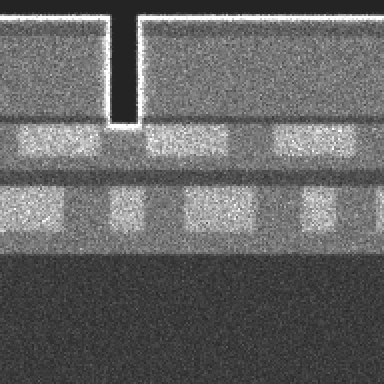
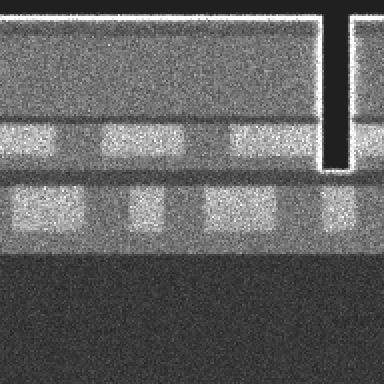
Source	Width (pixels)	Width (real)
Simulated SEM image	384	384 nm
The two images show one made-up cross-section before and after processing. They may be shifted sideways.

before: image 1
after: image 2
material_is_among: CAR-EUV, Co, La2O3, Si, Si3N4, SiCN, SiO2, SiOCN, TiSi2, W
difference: SiO2, removed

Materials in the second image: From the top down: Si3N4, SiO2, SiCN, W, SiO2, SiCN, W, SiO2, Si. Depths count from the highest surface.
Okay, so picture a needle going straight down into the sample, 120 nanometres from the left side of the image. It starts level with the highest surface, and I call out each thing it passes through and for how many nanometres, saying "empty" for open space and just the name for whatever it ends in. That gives Si3N4 20, SiO2 80, SiCN 8, W 32, SiO2 14, SiCN 16, SiO2 68, Si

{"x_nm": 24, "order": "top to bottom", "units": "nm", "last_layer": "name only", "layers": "Si3N4 20, SiO2 80, SiCN 8, W 32, SiO2 14, SiCN 16, W 46, SiO2 22, Si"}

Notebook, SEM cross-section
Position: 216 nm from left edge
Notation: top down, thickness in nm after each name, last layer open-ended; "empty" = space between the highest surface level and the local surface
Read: Si3N4 20, SiO2 80, SiCN 8, SiO2 46, SiCN 16, W 46, SiO2 22, Si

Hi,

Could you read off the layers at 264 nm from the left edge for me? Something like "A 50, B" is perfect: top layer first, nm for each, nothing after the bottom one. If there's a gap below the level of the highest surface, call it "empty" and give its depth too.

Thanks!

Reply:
Si3N4 20, SiO2 80, SiCN 8, W 32, SiO2 14, SiCN 16, W 46, SiO2 22, Si